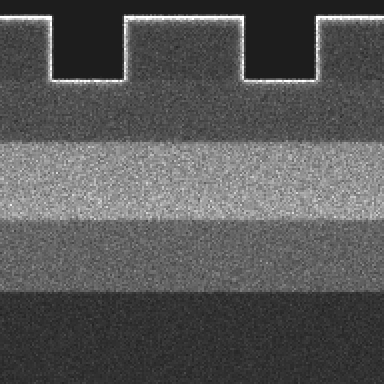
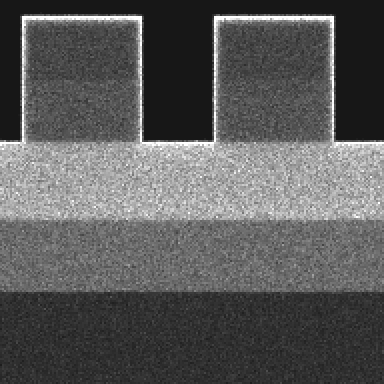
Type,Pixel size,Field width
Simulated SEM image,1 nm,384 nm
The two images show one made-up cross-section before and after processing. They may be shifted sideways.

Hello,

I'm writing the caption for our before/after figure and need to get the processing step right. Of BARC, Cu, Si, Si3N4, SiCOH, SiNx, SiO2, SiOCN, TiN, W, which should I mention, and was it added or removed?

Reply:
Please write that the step removed TiN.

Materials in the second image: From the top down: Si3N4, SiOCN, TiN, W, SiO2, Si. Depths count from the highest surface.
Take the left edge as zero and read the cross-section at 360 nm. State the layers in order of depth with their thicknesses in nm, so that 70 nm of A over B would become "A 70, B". empty 126, W 78, SiO2 72, Si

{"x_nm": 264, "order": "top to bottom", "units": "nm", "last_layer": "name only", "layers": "Si3N4 10, SiOCN 54, TiN 62, W 78, SiO2 72, Si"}